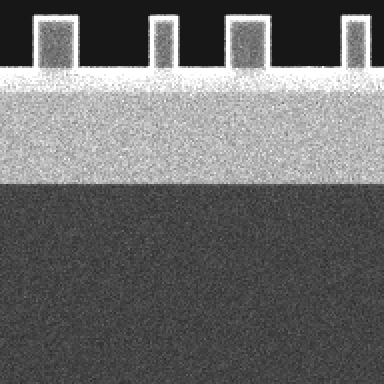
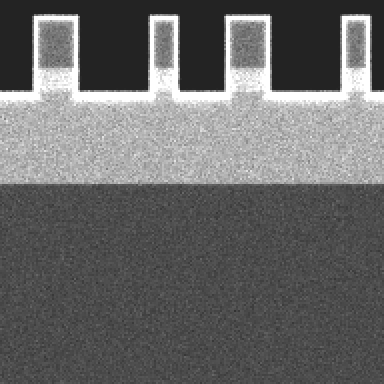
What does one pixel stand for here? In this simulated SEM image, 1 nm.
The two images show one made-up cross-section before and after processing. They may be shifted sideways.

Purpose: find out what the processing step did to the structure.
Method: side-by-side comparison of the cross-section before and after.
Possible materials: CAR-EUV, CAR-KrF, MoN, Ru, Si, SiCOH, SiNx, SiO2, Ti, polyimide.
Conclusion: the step removed Ru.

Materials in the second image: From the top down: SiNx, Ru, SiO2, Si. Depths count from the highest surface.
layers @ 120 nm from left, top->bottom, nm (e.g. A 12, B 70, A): empty 76, SiO2 92, Si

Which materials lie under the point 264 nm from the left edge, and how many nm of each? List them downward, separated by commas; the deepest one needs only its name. SiNx 52, Ru 24, SiO2 92, Si